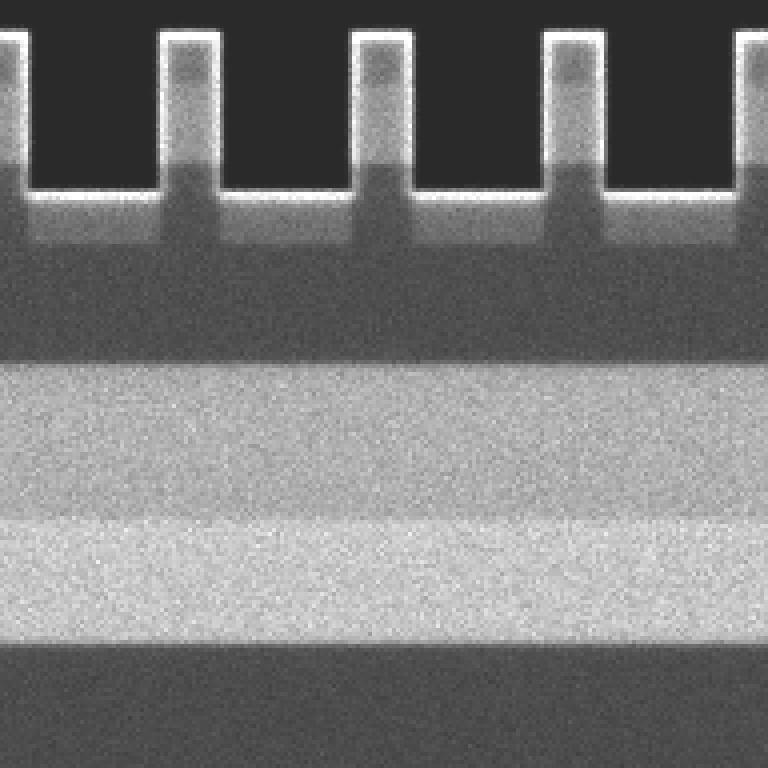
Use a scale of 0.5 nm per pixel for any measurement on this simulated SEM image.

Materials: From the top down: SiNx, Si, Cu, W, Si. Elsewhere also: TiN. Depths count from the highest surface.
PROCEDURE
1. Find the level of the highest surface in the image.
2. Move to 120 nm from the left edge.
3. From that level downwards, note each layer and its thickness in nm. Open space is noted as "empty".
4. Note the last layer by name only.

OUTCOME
empty 80, SiNx 26, Si 60, Cu 78, W 62, Si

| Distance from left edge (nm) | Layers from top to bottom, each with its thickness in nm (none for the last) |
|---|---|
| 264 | empty 80, SiNx 26, Si 60, Cu 78, W 62, Si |